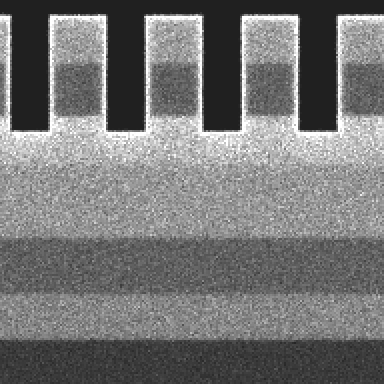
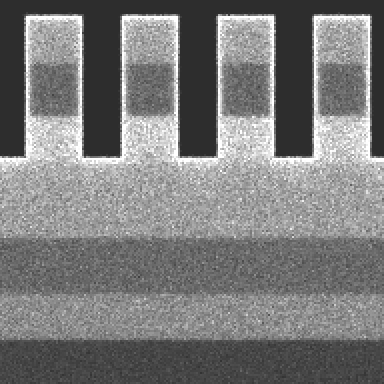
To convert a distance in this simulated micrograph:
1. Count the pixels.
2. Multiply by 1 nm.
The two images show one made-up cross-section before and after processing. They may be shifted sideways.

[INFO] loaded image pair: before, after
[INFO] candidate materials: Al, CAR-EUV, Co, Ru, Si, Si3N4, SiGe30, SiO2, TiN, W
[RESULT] removed W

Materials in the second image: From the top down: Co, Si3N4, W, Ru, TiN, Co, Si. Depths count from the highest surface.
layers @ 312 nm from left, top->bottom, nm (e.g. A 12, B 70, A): empty 142, W 6, Ru 74, TiN 56, Co 46, Si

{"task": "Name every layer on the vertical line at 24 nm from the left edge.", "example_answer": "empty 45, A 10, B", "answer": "empty 142, W 6, Ru 74, TiN 56, Co 46, Si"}